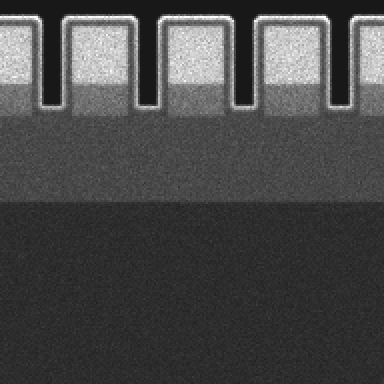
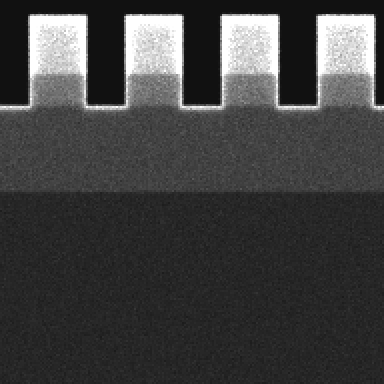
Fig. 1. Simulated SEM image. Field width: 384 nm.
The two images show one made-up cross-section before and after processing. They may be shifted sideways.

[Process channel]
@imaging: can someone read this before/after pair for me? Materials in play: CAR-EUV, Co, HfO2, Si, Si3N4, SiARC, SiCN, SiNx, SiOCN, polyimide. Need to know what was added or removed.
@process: SiNx removed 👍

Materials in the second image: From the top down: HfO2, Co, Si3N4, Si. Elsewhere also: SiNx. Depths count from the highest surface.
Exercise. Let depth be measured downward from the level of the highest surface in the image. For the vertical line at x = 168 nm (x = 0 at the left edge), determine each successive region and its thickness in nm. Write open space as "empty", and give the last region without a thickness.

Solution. HfO2 58, Co 32, Si3N4 86, Si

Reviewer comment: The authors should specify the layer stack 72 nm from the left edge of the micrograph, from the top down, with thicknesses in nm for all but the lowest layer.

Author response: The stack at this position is HfO2 58, Co 32, Si3N4 86, Si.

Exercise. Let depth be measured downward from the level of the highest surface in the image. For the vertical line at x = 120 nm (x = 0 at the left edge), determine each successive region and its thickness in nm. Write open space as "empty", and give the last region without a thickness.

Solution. empty 90, Si3N4 86, Si